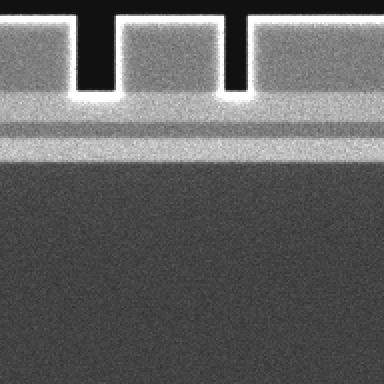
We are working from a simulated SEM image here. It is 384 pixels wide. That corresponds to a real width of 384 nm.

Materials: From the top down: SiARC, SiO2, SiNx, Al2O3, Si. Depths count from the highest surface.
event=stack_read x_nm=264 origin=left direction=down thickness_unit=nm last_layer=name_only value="SiARC 76, SiO2 30, SiNx 16, Al2O3 24, Si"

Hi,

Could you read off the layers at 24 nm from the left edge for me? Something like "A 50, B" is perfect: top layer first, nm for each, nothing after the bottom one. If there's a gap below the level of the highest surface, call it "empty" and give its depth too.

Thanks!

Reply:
SiARC 76, SiO2 30, SiNx 16, Al2O3 24, Si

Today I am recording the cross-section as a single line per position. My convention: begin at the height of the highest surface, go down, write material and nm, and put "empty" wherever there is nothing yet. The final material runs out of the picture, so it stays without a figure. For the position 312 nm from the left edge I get SiARC 76, SiO2 30, SiNx 16, Al2O3 24, Si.